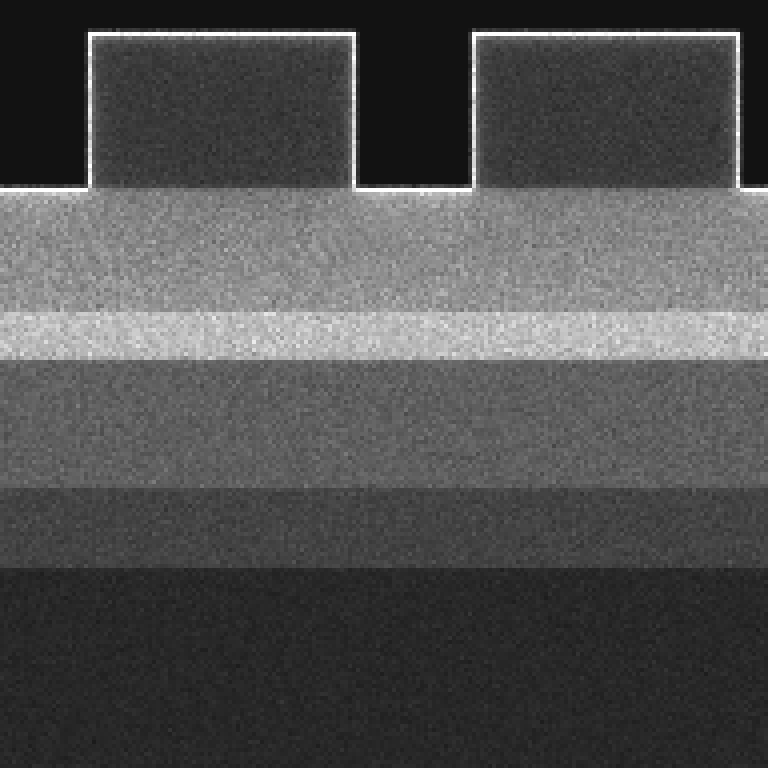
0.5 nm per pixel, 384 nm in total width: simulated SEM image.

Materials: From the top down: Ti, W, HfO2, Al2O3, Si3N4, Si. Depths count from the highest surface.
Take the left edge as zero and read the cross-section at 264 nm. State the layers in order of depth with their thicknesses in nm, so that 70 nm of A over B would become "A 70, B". Ti 78, W 62, HfO2 24, Al2O3 64, Si3N4 40, Si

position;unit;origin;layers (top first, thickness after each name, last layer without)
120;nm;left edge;Ti 78, W 62, HfO2 24, Al2O3 64, Si3N4 40, Si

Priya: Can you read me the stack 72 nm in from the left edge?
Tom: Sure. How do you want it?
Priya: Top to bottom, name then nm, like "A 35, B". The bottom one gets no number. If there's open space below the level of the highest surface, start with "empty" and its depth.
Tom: Ti 78, W 62, HfO2 24, Al2O3 64, Si3N4 40, Si